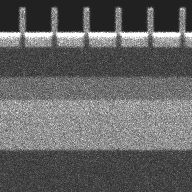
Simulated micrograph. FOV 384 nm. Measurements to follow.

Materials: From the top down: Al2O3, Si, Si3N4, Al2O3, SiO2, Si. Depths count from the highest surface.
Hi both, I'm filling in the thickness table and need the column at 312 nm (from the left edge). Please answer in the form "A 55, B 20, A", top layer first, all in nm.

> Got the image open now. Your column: empty 50, Al2O3 28, Si 60, Si3N4 46, Al2O3 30, SiO2 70, Si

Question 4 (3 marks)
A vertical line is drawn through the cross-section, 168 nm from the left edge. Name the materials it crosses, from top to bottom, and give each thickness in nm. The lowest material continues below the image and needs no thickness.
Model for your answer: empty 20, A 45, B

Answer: Si 138, Si3N4 46, Al2O3 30, SiO2 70, Si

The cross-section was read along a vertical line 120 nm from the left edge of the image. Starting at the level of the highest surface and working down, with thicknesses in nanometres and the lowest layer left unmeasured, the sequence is empty 50, Al2O3 28, Si 60, Si3N4 46, Al2O3 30, SiO2 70, Si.